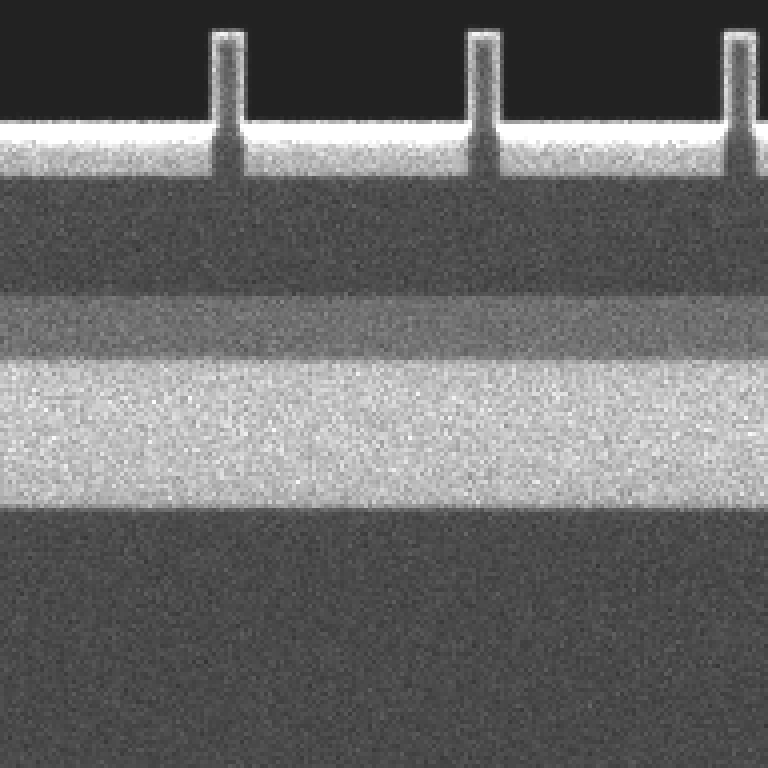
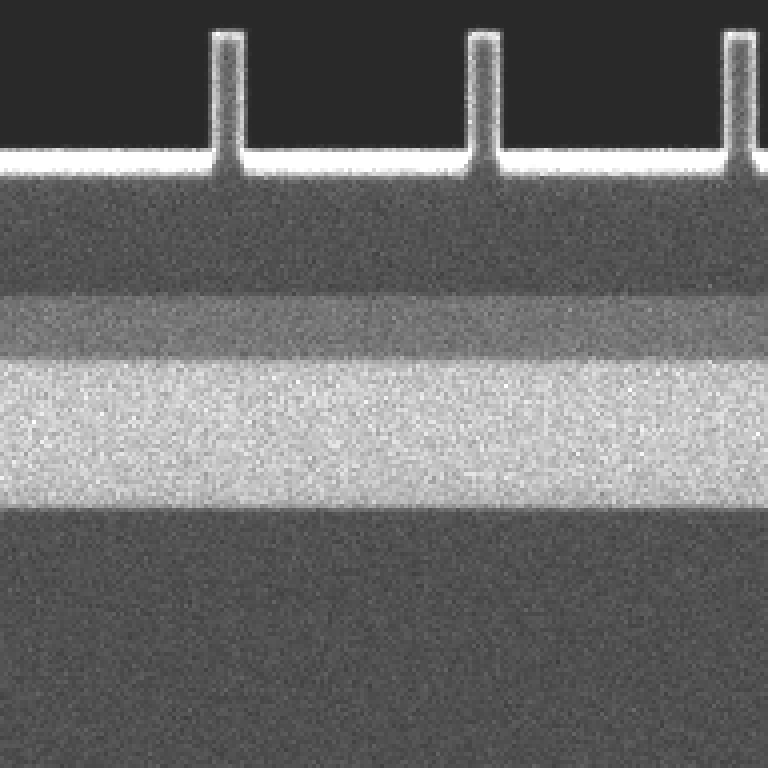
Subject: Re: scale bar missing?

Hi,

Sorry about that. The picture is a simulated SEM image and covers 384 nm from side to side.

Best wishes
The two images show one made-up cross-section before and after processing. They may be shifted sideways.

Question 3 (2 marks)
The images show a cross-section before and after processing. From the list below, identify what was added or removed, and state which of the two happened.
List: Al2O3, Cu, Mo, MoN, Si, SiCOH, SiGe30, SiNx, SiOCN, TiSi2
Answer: Al2O3 was removed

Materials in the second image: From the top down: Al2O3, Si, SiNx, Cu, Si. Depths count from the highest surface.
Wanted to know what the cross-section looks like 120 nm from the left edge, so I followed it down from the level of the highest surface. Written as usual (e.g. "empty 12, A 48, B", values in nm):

Si 132, SiNx 32, Cu 74, Si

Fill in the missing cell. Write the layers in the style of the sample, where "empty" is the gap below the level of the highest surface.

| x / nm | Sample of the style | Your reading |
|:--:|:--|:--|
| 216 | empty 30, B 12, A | empty 60, Al2O3 12, Si 60, SiNx 32, Cu 74, Si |